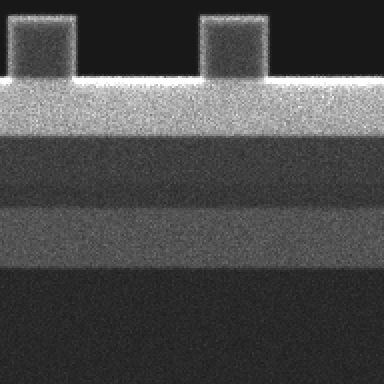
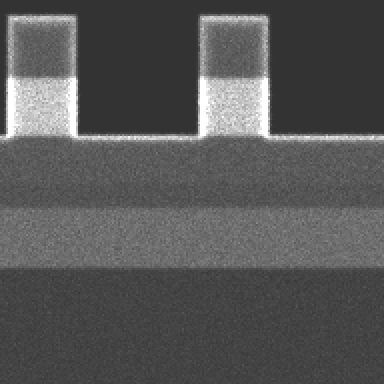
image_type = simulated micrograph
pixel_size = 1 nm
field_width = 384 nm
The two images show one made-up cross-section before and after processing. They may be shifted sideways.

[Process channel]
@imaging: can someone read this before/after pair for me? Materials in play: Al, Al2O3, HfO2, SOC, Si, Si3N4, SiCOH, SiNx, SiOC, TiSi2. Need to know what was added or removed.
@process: HfO2 removed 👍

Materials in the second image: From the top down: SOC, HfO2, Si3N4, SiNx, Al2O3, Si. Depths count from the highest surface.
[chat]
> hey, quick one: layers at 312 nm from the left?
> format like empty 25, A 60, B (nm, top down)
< empty 120, Si3N4 48, SiNx 24, Al2O3 60, Si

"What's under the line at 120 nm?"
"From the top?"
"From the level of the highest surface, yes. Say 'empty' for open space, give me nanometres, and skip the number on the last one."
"empty 120, Si3N4 48, SiNx 24, Al2O3 60, Si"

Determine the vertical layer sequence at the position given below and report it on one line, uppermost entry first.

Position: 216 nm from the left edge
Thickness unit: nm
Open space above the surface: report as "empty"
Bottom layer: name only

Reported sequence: SOC 62, HfO2 58, Si3N4 48, SiNx 24, Al2O3 60, Si